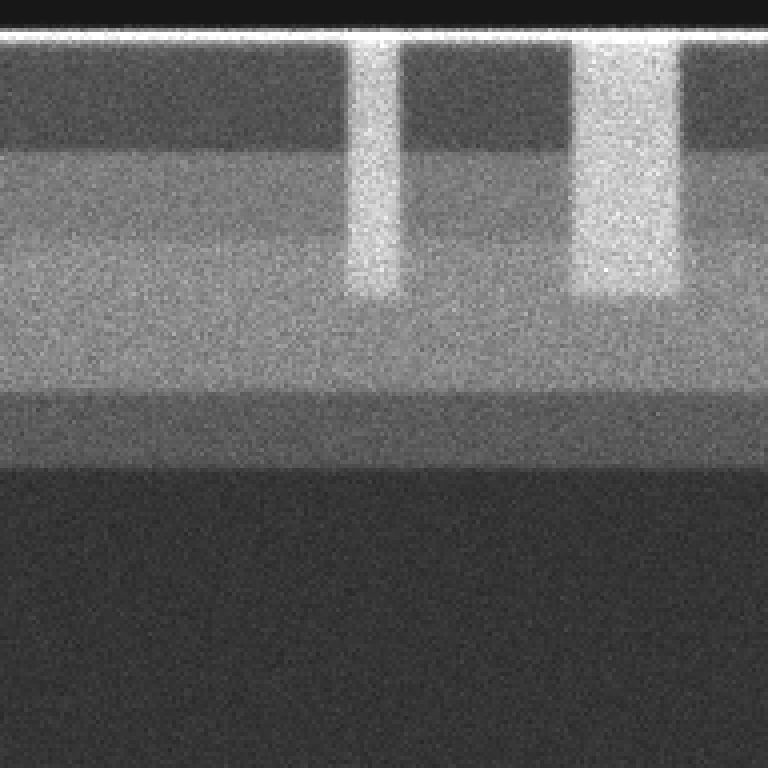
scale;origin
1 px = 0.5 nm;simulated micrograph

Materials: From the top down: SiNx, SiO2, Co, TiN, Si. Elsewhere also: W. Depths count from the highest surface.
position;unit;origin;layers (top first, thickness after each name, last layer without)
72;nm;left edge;SiNx 60, SiO2 44, Co 76, TiN 38, Si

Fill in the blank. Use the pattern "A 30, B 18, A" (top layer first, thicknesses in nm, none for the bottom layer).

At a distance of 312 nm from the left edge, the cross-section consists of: W 132, Co 48, TiN 38, Si